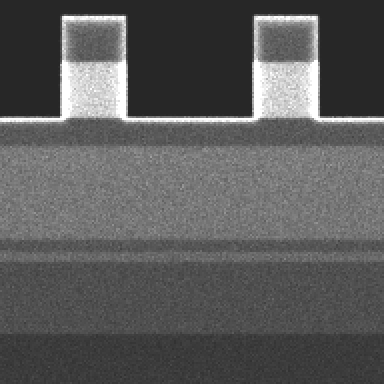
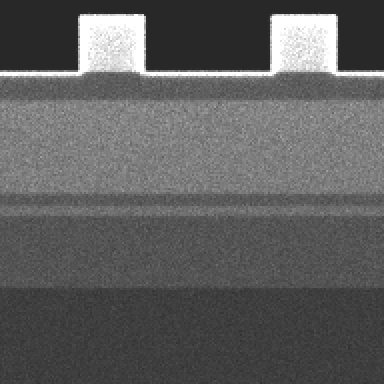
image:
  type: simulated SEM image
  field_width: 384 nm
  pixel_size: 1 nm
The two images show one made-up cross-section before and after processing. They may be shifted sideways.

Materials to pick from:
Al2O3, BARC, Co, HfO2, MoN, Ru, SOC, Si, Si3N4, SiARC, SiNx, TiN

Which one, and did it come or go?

SOC - removed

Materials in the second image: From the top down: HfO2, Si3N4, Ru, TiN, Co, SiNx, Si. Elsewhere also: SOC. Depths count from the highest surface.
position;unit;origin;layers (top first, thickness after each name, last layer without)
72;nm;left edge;empty 56, Si3N4 28, Ru 94, TiN 12, Co 10, SiNx 72, Si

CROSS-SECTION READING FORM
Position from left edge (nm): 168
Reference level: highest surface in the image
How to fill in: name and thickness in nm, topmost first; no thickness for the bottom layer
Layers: empty 56, Si3N4 28, Ru 94, TiN 12, Co 10, SiNx 72, Si